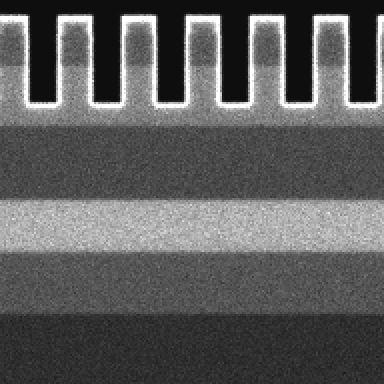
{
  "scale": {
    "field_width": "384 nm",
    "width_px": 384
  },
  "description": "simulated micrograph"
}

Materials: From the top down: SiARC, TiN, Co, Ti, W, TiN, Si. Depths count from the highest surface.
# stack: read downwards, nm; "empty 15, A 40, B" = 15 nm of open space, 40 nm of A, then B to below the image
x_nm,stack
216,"SiARC 18, TiN 32, Co 60, Ti 74, W 52, TiN 62, Si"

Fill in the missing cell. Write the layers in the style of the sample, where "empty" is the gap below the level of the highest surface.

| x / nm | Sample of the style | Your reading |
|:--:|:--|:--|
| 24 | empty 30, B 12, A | SiARC 18, TiN 32, Co 60, Ti 74, W 52, TiN 62, Si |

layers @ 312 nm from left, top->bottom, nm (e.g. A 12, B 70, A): empty 88, Co 22, Ti 74, W 52, TiN 62, Si